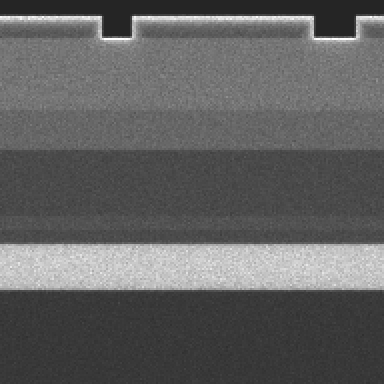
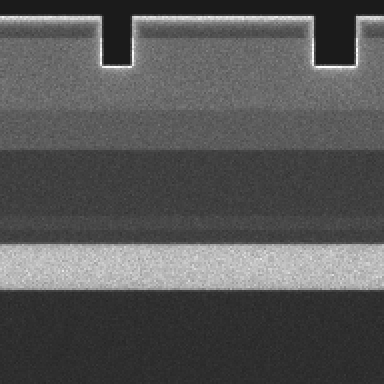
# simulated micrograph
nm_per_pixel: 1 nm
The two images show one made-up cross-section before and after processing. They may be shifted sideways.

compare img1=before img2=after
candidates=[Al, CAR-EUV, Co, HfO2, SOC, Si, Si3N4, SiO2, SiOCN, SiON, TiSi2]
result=removed:Co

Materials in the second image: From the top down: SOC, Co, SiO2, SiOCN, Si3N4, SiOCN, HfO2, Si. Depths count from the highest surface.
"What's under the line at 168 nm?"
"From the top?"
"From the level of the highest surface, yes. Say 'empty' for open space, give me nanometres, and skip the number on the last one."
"SOC 22, Co 72, SiO2 40, SiOCN 66, Si3N4 14, SiOCN 14, HfO2 46, Si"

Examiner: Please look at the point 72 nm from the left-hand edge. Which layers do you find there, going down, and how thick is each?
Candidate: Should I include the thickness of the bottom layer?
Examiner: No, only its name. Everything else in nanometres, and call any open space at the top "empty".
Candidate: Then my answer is SOC 22, Co 72, SiO2 40, SiOCN 66, Si3N4 14, SiOCN 14, HfO2 46, Si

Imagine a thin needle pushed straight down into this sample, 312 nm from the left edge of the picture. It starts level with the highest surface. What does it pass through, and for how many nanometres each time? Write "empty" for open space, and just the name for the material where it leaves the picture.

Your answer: SOC 22, Co 72, SiO2 40, SiOCN 66, Si3N4 14, SiOCN 14, HfO2 46, Si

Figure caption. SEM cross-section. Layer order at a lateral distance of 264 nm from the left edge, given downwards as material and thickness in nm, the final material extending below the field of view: SOC 22, Co 72, SiO2 40, SiOCN 66, Si3N4 14, SiOCN 14, HfO2 46, Si